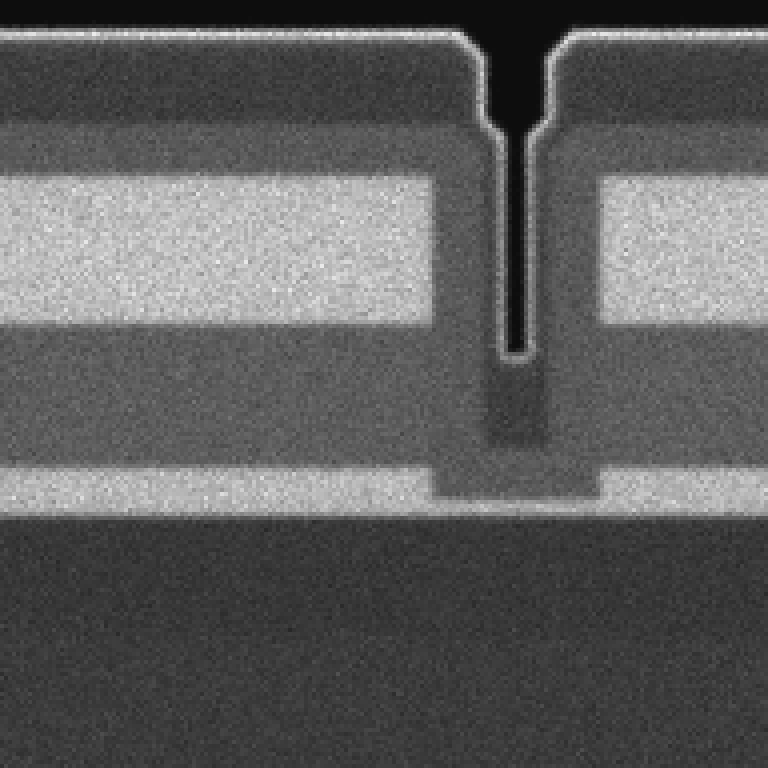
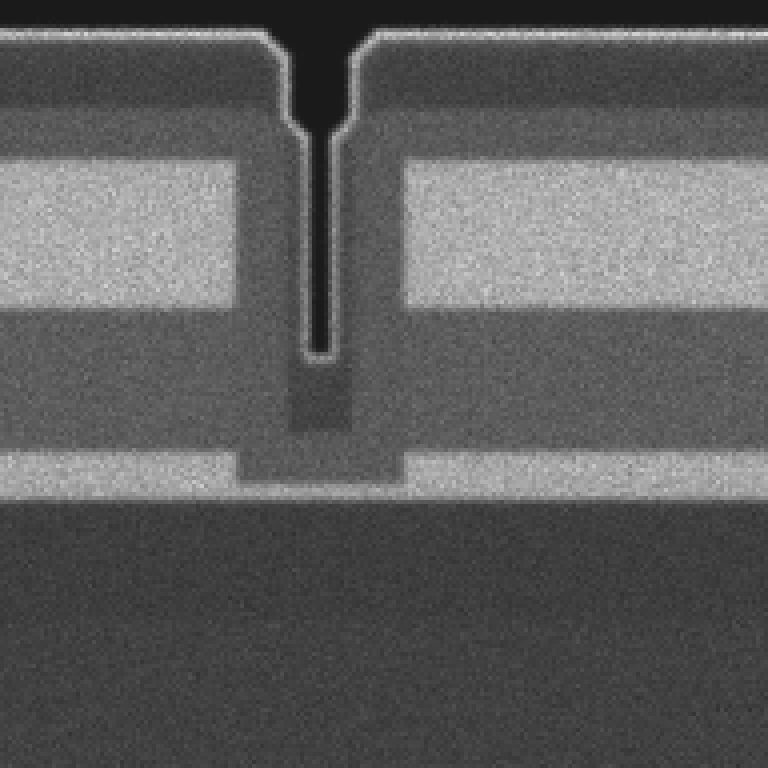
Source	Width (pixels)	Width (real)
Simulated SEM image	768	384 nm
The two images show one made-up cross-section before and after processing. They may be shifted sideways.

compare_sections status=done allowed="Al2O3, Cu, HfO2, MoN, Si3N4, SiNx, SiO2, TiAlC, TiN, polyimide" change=removed material="TiN"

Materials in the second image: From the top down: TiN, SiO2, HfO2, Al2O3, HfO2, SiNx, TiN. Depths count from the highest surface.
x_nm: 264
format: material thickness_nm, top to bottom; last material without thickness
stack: TiN 38, SiO2 26, HfO2 74, Al2O3 72, HfO2 24, SiNx 60, TiN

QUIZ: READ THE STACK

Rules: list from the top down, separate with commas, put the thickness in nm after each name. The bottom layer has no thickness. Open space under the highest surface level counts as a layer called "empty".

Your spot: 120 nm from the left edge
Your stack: TiN 38, SiO2 188, HfO2 8, SiNx 60, TiN